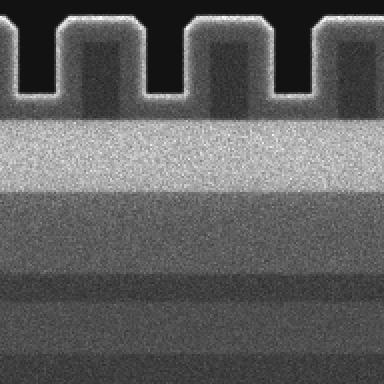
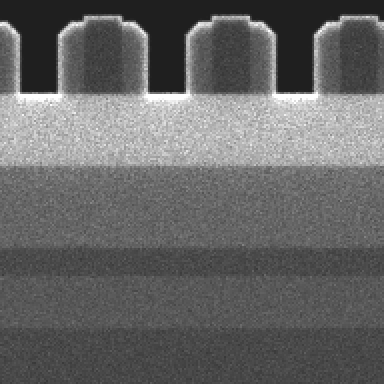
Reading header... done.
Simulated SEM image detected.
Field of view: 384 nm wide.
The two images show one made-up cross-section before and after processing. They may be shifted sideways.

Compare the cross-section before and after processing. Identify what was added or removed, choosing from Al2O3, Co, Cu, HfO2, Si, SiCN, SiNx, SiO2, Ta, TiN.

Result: SiO2 removed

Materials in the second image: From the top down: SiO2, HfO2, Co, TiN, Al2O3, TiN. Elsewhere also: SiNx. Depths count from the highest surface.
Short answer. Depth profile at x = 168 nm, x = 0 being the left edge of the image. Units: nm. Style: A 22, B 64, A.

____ empty 78, HfO2 72, Co 82, TiN 28, Al2O3 52, TiN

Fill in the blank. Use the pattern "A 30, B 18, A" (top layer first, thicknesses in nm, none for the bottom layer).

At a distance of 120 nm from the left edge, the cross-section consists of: SiNx 78, HfO2 72, Co 82, TiN 28, Al2O3 52, TiN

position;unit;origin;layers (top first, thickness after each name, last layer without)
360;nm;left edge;SiNx 78, HfO2 72, Co 82, TiN 28, Al2O3 52, TiN